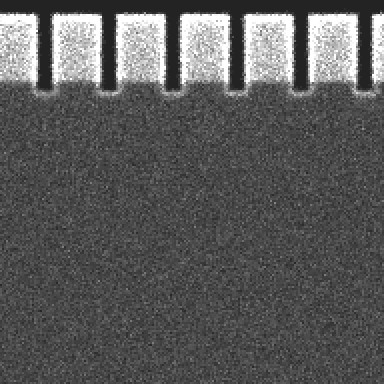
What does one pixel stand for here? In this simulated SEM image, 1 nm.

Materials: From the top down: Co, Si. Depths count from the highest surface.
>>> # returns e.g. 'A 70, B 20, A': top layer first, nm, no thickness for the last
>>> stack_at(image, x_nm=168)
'empty 76, Si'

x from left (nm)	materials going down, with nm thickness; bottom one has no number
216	Co 66, Si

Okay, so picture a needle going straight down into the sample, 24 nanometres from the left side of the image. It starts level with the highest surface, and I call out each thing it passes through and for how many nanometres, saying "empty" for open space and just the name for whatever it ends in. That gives Co 66, Si